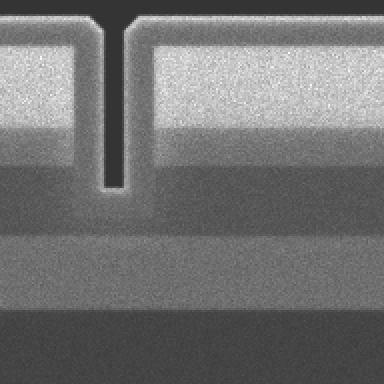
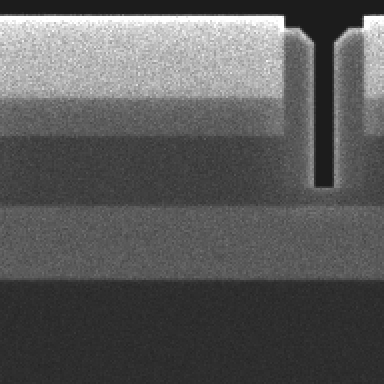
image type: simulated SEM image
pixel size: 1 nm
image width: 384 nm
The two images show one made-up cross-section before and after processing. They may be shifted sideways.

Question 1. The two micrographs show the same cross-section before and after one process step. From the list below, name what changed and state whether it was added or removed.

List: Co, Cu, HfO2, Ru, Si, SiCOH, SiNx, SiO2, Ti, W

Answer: SiO2, removed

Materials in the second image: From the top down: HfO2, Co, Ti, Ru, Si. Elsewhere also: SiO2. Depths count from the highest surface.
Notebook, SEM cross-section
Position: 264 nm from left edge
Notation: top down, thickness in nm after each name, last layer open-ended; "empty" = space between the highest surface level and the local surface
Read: HfO2 82, Co 38, Ti 70, Ru 74, Si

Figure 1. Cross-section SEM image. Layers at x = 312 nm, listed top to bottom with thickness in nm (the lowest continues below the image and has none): empty 26, SiO2 146, Ti 18, Ru 74, Si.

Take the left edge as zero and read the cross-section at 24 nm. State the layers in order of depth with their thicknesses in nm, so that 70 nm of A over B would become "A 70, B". HfO2 82, Co 38, Ti 70, Ru 74, Si